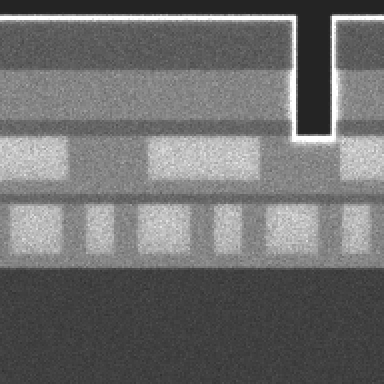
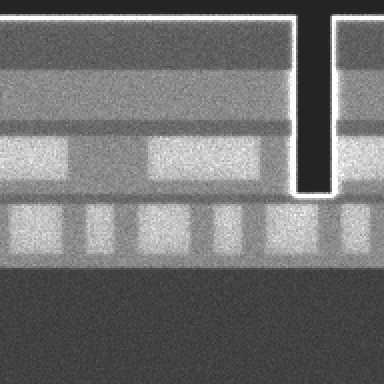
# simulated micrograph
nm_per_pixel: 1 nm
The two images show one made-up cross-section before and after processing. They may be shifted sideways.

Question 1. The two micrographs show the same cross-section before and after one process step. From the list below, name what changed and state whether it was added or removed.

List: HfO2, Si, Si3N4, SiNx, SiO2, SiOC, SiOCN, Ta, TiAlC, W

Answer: SiO2, removed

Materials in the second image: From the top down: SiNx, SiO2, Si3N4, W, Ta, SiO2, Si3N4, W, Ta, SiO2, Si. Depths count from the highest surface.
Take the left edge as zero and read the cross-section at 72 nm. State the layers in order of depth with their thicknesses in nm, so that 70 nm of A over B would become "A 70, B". SiNx 54, SiO2 50, Si3N4 16, SiO2 58, Si3N4 10, SiO2 64, Si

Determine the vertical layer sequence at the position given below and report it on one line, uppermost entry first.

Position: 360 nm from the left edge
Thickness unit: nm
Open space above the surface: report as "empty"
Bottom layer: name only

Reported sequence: SiNx 54, SiO2 50, Si3N4 16, W 34, Ta 10, SiO2 14, Si3N4 10, Ta 50, SiO2 14, Si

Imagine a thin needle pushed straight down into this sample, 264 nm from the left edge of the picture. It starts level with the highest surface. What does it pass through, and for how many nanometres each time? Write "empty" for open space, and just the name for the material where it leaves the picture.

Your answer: SiNx 54, SiO2 50, Si3N4 16, SiO2 58, Si3N4 10, SiO2 64, Si